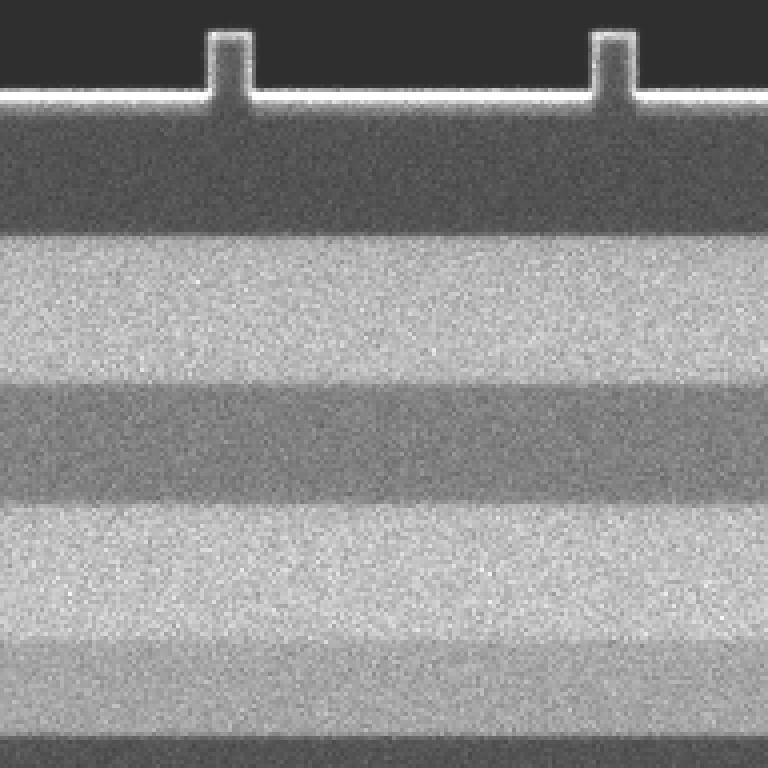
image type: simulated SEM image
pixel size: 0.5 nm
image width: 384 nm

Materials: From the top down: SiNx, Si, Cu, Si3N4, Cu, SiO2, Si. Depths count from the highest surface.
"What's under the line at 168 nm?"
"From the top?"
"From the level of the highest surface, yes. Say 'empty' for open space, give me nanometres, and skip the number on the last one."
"empty 30, SiNx 12, Si 60, Cu 74, Si3N4 60, Cu 68, SiO2 48, Si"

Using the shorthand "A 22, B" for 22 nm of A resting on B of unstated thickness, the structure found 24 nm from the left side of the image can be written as empty 30, SiNx 12, Si 60, Cu 74, Si3N4 60, Cu 68, SiO2 48, Si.